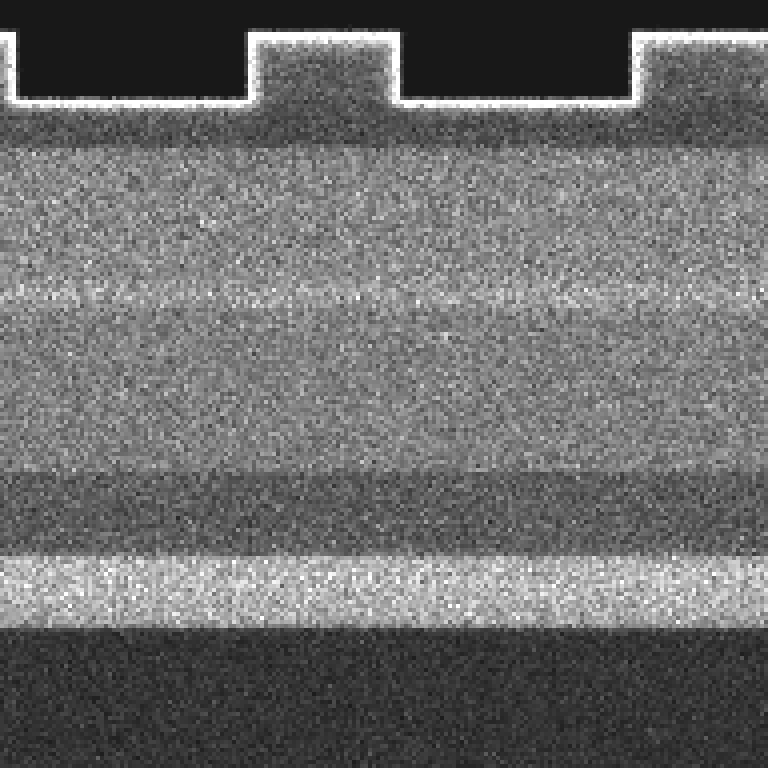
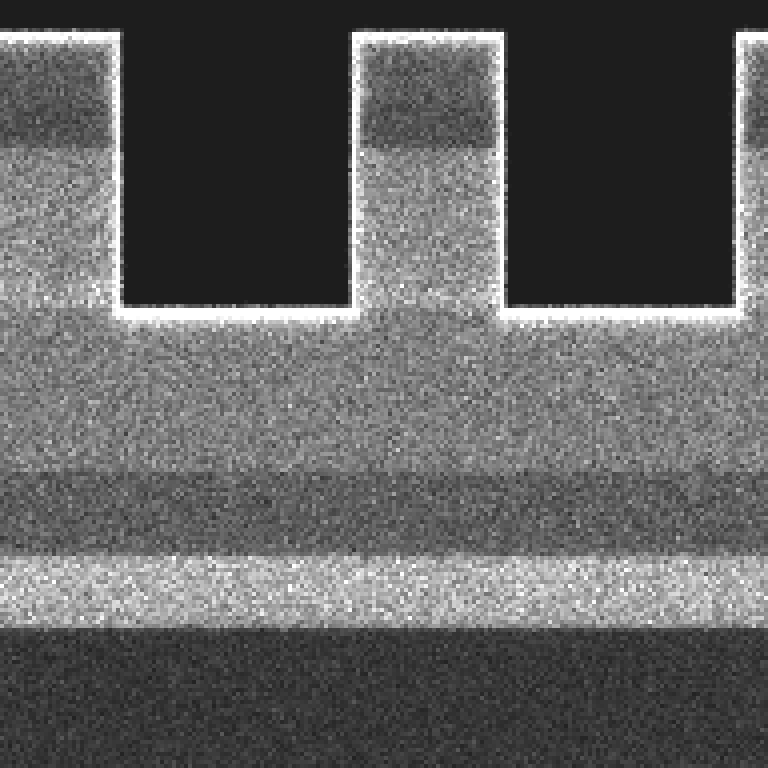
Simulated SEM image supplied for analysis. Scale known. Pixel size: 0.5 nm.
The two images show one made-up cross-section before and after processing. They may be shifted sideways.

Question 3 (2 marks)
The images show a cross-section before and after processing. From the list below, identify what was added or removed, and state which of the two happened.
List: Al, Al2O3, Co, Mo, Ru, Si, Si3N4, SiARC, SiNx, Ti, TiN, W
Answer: Co and Ru and SiNx was removed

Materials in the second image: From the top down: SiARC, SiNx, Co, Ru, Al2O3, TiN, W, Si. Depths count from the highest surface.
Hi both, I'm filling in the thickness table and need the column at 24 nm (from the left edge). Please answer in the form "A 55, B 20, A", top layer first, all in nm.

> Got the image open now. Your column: SiARC 34, SiNx 24, Co 68, Ru 12, Al2O3 82, TiN 42, W 36, Si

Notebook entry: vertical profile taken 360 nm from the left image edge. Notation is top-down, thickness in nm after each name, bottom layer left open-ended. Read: empty 138, Al2O3 82, TiN 42, W 36, Si